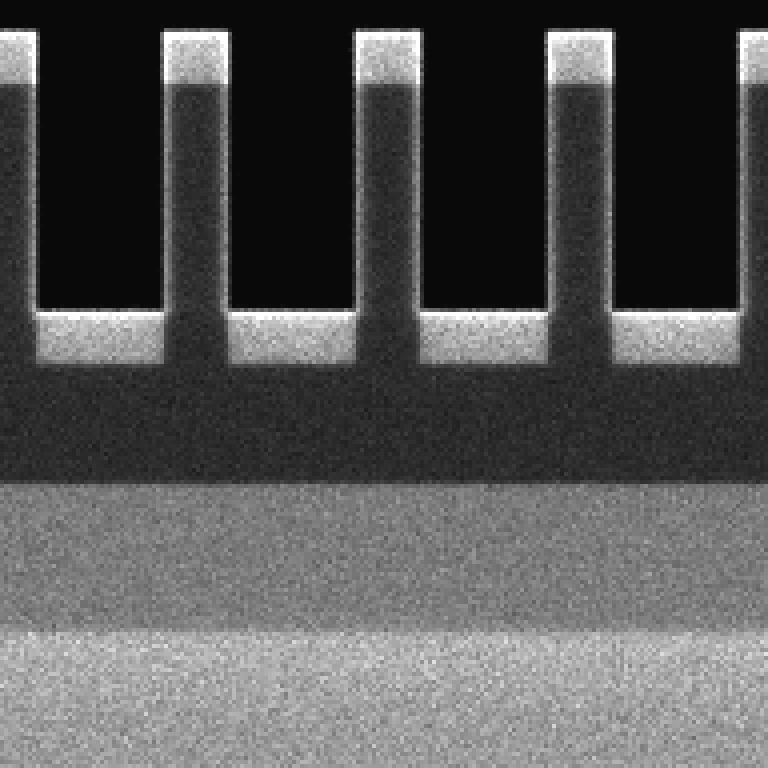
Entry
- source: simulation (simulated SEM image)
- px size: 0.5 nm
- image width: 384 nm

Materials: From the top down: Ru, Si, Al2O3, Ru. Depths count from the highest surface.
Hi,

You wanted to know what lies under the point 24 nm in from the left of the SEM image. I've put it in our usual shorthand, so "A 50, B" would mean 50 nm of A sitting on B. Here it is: empty 140, Ru 26, Si 60, Al2O3 74, Ru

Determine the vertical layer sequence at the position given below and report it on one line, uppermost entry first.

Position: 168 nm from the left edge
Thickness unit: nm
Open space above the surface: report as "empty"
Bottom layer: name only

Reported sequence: empty 140, Ru 26, Si 60, Al2O3 74, Ru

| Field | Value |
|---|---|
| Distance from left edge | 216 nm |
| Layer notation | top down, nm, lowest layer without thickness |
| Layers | empty 140, Ru 26, Si 60, Al2O3 74, Ru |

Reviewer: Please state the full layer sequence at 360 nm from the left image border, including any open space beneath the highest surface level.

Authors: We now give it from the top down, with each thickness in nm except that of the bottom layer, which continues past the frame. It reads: empty 140, Ru 26, Si 60, Al2O3 74, Ru